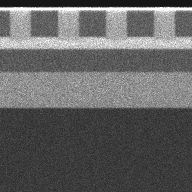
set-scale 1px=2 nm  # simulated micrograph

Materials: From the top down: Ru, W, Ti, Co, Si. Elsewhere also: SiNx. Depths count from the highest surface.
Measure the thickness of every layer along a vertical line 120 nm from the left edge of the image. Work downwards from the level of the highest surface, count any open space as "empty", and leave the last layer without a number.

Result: Ru 64, W 18, Ti 46, Co 72, Si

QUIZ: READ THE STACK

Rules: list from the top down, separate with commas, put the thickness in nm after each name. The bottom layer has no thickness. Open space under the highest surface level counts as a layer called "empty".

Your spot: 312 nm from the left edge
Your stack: Ru 64, W 18, Ti 46, Co 72, Si